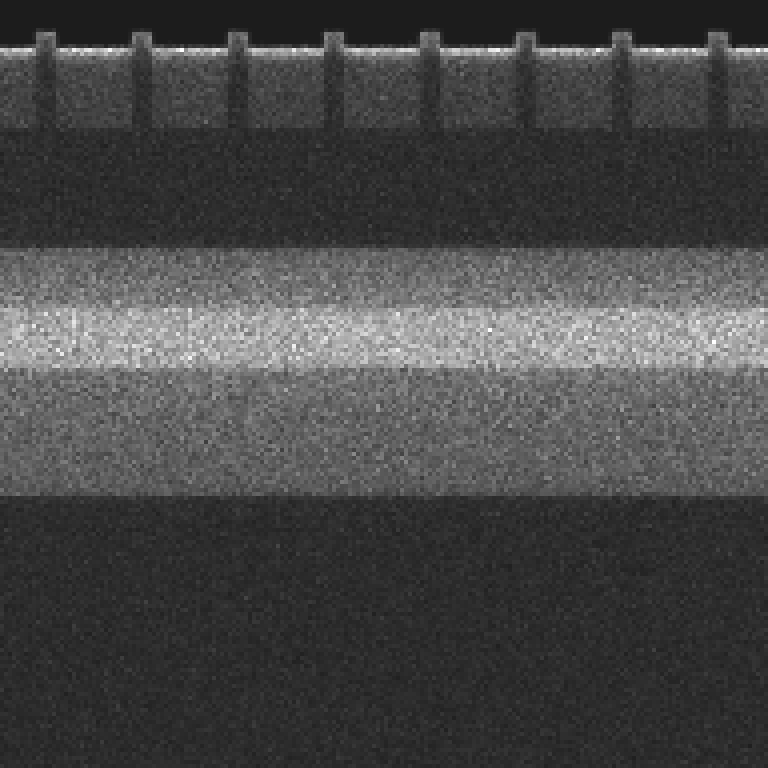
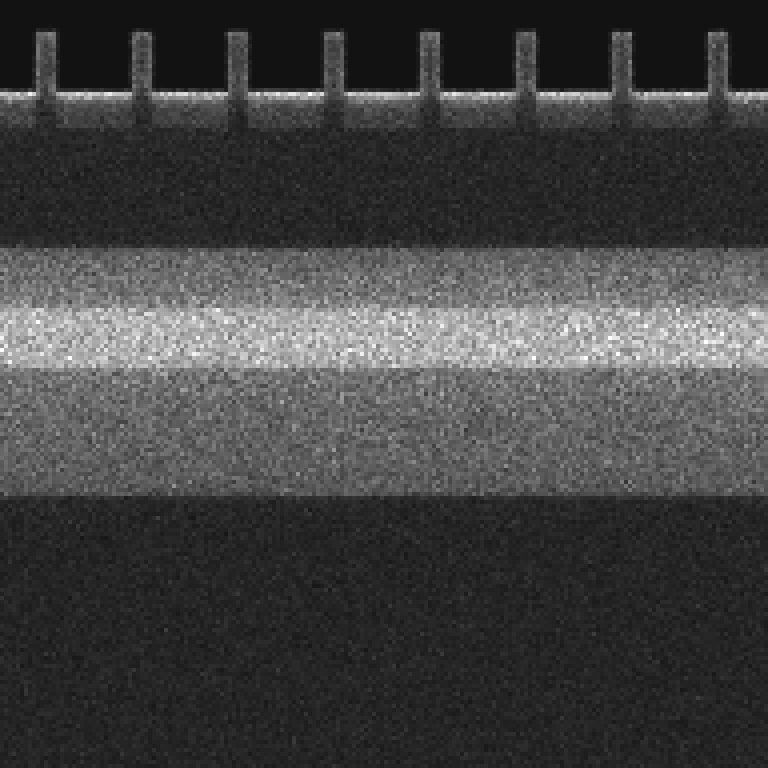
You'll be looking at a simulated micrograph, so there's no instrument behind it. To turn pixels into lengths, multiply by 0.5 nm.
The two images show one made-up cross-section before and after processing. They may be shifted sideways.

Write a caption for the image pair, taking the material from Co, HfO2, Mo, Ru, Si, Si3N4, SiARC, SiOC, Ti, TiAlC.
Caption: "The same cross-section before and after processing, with Si3N4 removed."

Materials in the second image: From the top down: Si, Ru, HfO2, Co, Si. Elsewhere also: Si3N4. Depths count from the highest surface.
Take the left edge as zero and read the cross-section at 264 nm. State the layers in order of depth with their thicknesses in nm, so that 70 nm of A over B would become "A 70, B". Si 108, Ru 30, HfO2 30, Co 64, Si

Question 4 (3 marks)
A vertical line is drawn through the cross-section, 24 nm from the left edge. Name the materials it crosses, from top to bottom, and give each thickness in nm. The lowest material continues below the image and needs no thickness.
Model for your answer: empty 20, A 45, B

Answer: Si 108, Ru 30, HfO2 30, Co 64, Si